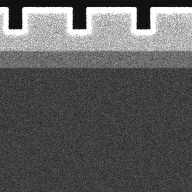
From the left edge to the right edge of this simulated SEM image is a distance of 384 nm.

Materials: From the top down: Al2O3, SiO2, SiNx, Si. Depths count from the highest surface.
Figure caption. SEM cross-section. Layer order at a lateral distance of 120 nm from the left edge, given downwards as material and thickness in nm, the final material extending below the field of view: Al2O3 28, SiO2 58, SiNx 34, Si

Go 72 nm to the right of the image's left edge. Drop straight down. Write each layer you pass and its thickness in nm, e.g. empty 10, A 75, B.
Al2O3 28, SiO2 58, SiNx 34, Si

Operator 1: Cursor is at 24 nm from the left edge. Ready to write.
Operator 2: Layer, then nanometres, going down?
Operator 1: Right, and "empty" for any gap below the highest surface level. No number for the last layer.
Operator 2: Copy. empty 44, SiO2 42, SiNx 34, Si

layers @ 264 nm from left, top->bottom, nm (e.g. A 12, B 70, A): Al2O3 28, SiO2 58, SiNx 34, Si